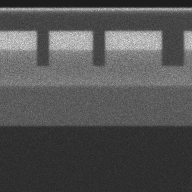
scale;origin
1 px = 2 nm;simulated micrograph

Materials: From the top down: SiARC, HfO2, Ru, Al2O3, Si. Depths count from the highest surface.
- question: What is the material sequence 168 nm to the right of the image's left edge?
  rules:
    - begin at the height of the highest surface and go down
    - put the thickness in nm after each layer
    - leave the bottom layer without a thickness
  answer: SiARC 46, HfO2 38, Ru 72, Al2O3 80, Si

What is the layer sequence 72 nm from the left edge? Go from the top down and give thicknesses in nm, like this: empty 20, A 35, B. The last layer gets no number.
SiARC 46, HfO2 38, Ru 72, Al2O3 80, Si